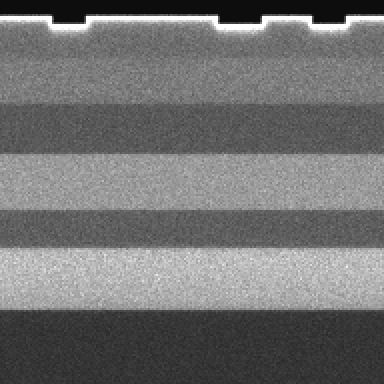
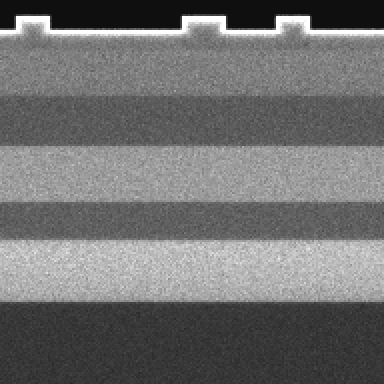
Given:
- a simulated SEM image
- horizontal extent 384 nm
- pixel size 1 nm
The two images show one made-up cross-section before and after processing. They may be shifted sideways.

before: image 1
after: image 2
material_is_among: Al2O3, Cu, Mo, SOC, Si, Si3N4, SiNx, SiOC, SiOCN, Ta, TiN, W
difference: Si3N4, removed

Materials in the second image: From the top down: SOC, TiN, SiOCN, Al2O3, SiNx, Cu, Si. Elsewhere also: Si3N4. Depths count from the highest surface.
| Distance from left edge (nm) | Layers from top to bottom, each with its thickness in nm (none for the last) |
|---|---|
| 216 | SOC 34, TiN 46, SiOCN 50, Al2O3 56, SiNx 38, Cu 62, Si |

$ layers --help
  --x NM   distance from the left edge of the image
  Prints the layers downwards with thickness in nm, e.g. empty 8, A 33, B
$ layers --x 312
empty 14, Si3N4 20, TiN 46, SiOCN 50, Al2O3 56, SiNx 38, Cu 62, Si